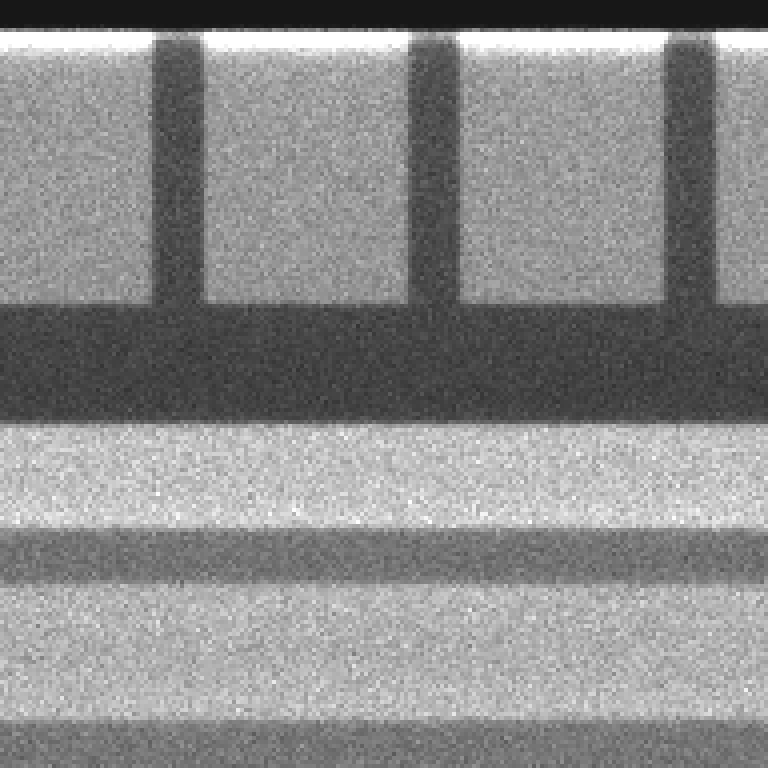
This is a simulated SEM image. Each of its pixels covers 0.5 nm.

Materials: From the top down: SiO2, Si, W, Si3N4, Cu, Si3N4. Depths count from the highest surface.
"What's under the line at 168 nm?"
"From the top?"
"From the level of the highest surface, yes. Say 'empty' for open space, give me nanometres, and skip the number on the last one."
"SiO2 136, Si 60, W 52, Si3N4 28, Cu 68, Si3N4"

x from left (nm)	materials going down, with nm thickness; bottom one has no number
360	SiO2 136, Si 60, W 52, Si3N4 28, Cu 68, Si3N4